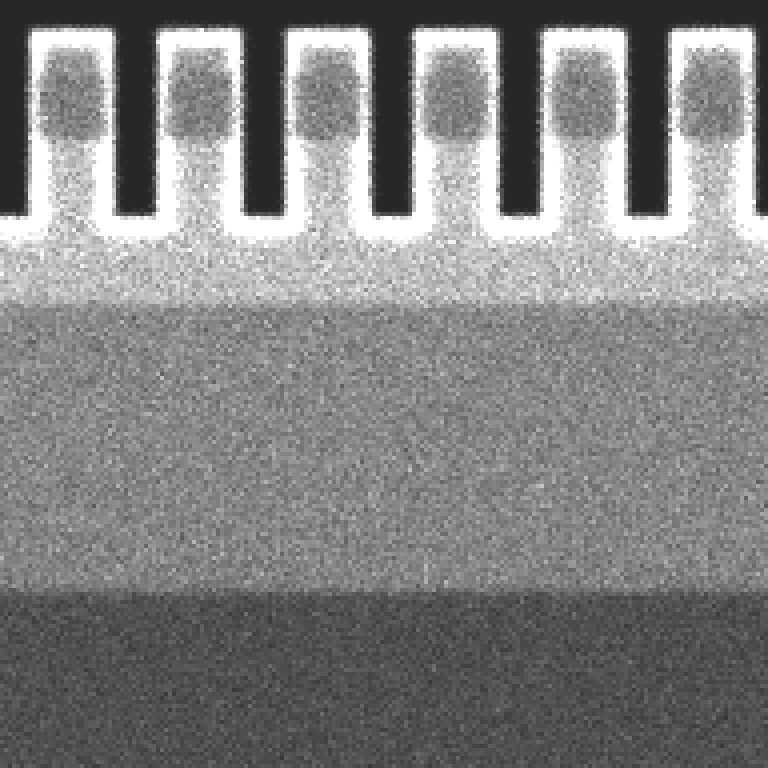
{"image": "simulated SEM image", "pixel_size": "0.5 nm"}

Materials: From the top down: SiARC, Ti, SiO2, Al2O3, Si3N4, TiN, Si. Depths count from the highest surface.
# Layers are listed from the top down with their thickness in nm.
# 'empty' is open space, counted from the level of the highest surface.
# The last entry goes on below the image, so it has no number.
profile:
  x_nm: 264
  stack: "empty 94, Al2O3 42, Si3N4 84, TiN 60, Si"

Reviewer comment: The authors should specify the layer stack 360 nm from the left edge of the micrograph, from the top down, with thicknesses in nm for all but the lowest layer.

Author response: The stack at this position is SiARC 20, Ti 34, SiO2 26, Al2O3 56, Si3N4 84, TiN 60, Si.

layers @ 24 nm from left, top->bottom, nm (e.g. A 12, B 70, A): SiARC 20, Ti 34, SiO2 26, Al2O3 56, Si3N4 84, TiN 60, Si